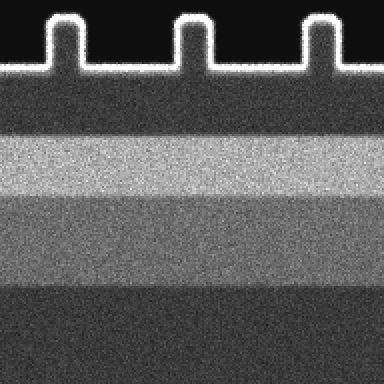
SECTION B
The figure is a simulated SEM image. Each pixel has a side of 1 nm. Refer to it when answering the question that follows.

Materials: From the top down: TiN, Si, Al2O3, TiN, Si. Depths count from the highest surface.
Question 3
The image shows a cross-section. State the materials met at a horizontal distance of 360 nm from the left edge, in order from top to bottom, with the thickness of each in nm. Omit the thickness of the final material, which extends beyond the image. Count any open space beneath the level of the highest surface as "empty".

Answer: empty 50, TiN 10, Si 60, Al2O3 60, TiN 90, Si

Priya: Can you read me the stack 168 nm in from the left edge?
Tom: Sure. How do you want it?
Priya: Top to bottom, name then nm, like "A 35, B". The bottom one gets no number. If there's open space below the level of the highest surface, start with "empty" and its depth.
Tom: empty 50, TiN 10, Si 60, Al2O3 60, TiN 90, Si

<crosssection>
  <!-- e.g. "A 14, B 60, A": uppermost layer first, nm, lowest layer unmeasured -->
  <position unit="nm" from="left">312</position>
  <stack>TiN 10, Si 110, Al2O3 60, TiN 90, Si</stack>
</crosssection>